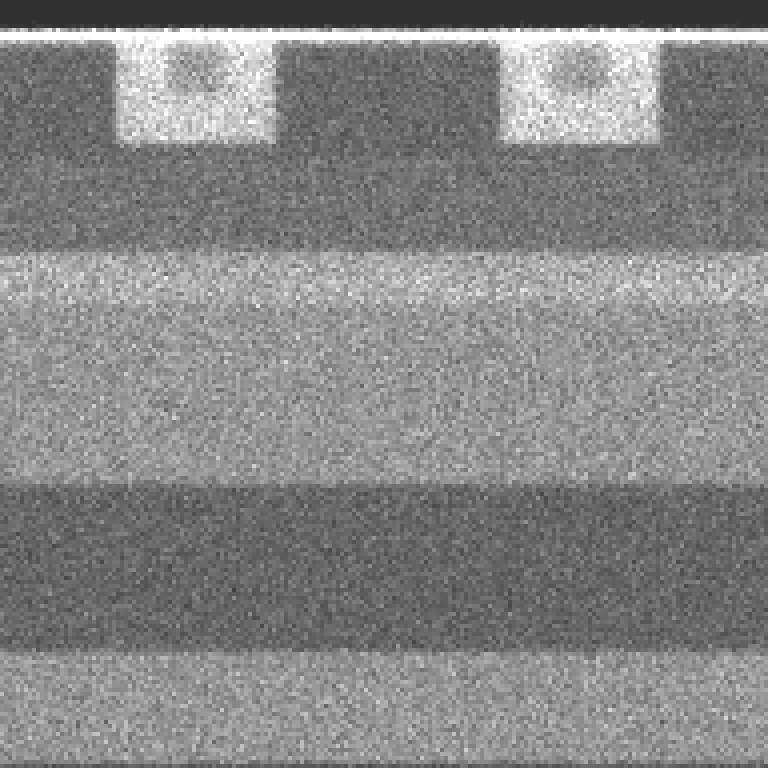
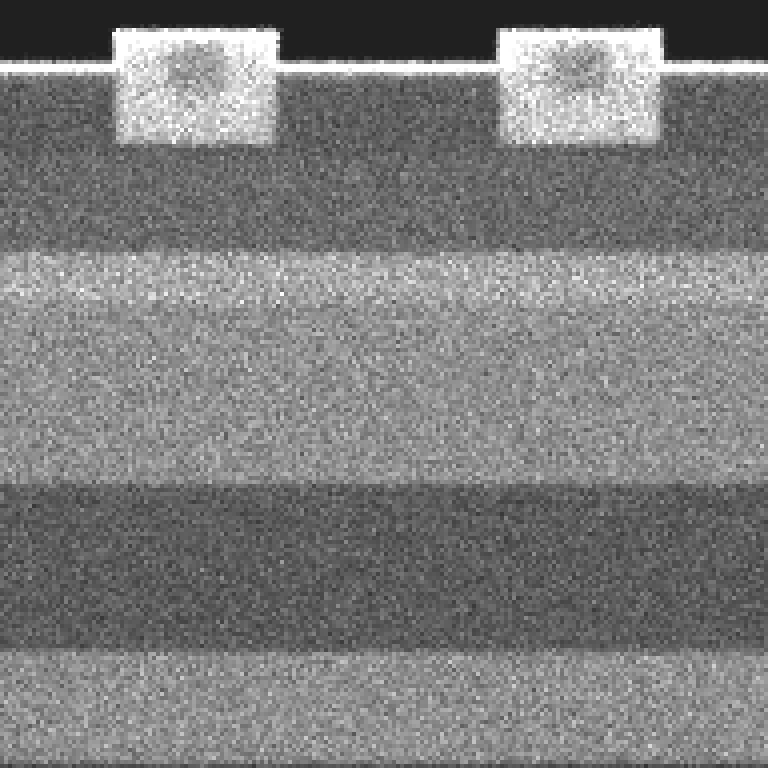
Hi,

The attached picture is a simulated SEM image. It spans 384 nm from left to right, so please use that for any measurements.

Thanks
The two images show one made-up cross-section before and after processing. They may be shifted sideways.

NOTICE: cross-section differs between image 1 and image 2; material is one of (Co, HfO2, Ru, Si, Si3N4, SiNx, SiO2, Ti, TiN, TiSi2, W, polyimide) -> removed: SiNx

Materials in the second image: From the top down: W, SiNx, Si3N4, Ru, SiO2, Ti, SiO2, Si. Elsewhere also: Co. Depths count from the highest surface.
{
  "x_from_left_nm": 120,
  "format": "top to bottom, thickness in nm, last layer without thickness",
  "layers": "W 56, SiNx 6, Si3N4 48, Ru 26, SiO2 90, Ti 84, SiO2 56, Si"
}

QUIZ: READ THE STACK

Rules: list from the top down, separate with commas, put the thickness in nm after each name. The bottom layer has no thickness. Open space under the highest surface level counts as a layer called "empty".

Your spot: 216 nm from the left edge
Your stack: empty 16, SiNx 46, Si3N4 48, Ru 26, SiO2 90, Ti 84, SiO2 56, Si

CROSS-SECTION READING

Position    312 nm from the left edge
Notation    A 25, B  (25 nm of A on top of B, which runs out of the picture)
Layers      W 56, SiNx 6, Si3N4 48, Ru 26, SiO2 90, Ti 84, SiO2 56, Si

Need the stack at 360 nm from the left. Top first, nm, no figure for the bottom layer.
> empty 16, SiNx 46, Si3N4 48, Ru 26, SiO2 90, Ti 84, SiO2 56, Si